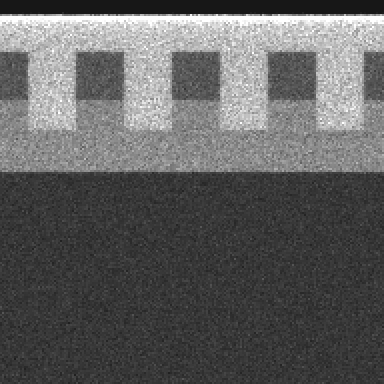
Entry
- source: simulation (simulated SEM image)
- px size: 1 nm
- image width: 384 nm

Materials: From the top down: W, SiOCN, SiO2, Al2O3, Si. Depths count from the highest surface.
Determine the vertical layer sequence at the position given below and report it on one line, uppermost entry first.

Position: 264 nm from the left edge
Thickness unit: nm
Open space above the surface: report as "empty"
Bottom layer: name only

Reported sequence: W 114, SiO2 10, Al2O3 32, Si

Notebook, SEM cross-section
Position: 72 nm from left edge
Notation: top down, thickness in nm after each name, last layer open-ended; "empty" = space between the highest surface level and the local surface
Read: W 114, SiO2 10, Al2O3 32, Si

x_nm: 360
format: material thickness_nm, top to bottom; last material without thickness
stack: W 114, SiO2 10, Al2O3 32, Si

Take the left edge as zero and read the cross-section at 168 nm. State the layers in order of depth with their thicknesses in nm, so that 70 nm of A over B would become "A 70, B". W 114, SiO2 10, Al2O3 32, Si